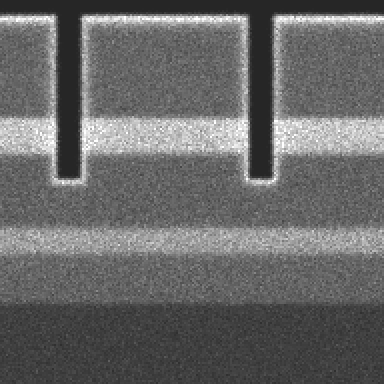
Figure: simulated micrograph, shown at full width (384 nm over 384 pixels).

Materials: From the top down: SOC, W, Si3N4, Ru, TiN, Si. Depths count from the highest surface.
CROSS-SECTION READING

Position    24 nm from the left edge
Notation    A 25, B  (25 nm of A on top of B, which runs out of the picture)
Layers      SOC 102, W 36, Si3N4 74, Ru 26, TiN 50, Si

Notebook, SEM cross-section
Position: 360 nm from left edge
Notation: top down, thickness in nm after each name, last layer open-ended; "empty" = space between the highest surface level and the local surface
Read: SOC 102, W 36, Si3N4 74, Ru 26, TiN 50, Si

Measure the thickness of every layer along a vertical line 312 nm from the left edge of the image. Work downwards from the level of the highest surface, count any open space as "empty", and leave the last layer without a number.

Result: SOC 102, W 36, Si3N4 74, Ru 26, TiN 50, Si